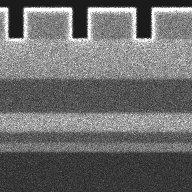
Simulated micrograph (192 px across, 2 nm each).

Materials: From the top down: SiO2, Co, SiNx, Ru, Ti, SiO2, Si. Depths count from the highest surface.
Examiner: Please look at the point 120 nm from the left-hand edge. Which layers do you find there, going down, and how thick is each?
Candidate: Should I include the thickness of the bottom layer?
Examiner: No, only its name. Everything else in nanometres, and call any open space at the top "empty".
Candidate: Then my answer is SiO2 62, Co 80, SiNx 68, Ru 38, Ti 22, SiO2 18, Si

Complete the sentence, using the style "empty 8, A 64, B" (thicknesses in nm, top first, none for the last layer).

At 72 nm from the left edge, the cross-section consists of SiO2 62, Co 80, SiNx 68, Ru 38, Ti 22, SiO2 18, Si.